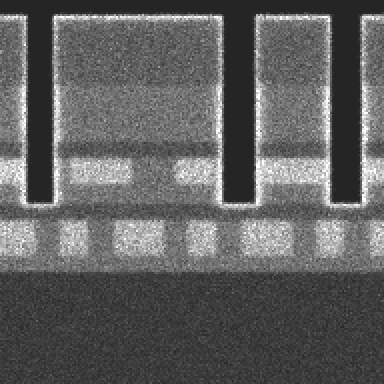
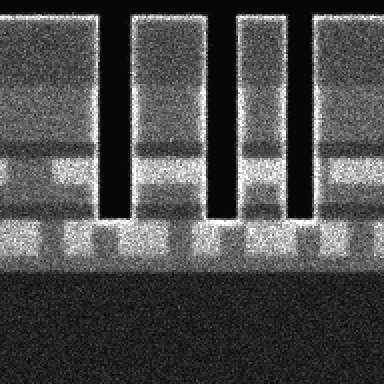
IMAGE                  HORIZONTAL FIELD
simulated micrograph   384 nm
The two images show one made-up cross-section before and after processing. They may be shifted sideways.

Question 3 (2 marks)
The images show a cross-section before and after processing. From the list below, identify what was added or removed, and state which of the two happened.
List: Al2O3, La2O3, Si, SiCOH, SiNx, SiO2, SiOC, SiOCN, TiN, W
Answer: SiNx was removed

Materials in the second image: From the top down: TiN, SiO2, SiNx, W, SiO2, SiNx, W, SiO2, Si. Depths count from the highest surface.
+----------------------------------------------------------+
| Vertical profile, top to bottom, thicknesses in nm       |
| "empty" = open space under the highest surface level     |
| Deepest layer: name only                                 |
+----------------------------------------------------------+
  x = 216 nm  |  empty 204, W 36, SiO2 16, Si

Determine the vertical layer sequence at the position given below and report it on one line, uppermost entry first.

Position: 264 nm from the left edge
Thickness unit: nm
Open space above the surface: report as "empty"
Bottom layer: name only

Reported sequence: TiN 70, SiO2 56, SiNx 16, W 26, SiO2 20, SiNx 16, W 36, SiO2 16, Si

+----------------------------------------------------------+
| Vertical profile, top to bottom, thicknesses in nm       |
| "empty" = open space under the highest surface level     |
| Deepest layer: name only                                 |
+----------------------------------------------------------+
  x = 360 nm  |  TiN 70, SiO2 56, SiNx 16, W 26, SiO2 20, SiNx 16, SiO2 52, Si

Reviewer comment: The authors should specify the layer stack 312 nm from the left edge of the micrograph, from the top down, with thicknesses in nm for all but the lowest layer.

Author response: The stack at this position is empty 204, SiO2 52, Si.